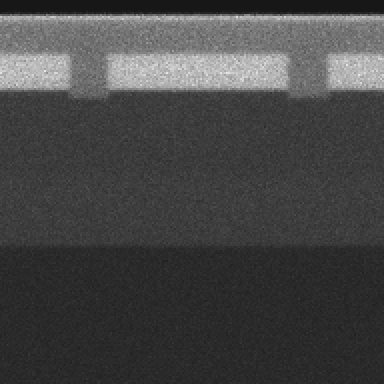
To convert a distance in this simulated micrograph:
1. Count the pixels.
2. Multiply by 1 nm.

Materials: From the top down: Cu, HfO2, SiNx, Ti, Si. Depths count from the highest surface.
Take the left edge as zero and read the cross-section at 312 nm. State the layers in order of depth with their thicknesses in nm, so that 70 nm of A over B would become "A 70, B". Cu 82, SiNx 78, Ti 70, Si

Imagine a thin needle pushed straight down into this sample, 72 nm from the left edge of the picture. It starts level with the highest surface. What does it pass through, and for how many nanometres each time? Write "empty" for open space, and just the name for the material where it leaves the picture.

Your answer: Cu 82, SiNx 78, Ti 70, Si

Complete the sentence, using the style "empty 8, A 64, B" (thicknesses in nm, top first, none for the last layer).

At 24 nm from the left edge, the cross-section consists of Cu 38, HfO2 36, SiNx 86, Ti 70, Si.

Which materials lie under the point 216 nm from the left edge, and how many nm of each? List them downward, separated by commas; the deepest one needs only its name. Cu 38, HfO2 36, SiNx 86, Ti 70, Si